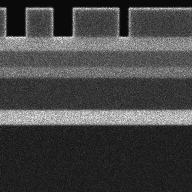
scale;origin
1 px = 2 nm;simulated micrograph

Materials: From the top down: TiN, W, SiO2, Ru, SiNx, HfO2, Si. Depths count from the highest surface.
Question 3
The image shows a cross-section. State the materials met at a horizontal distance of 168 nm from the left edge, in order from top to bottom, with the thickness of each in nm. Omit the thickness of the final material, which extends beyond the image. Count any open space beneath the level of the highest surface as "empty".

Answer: TiN 58, W 28, SiO2 32, Ru 22, SiNx 64, HfO2 30, Si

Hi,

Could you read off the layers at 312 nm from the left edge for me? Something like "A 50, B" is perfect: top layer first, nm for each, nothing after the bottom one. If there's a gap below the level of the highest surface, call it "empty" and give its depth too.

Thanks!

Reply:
TiN 58, W 28, SiO2 32, Ru 22, SiNx 64, HfO2 30, Si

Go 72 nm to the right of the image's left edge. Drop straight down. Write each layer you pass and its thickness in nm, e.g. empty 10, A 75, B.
TiN 58, W 28, SiO2 32, Ru 22, SiNx 64, HfO2 30, Si